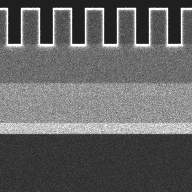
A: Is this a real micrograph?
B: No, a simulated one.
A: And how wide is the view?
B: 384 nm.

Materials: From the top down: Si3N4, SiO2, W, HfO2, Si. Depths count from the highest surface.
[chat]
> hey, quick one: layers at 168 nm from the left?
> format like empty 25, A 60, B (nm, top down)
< empty 72, SiO2 78, W 80, HfO2 22, Si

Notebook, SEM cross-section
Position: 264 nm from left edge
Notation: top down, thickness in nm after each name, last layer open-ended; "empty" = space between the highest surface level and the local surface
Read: Si3N4 72, SiO2 78, W 80, HfO2 22, Si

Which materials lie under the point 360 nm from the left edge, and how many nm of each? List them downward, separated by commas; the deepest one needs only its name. empty 72, SiO2 78, W 80, HfO2 22, Si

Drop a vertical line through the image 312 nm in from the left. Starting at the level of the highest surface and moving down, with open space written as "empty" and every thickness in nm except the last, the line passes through Si3N4 72, SiO2 78, W 80, HfO2 22, Si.